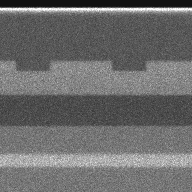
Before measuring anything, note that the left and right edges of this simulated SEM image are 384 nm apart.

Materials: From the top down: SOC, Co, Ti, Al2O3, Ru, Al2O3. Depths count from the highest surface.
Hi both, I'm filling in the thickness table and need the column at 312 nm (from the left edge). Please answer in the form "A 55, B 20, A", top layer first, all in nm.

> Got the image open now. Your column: SOC 106, Co 68, Ti 62, Al2O3 56, Ru 26, Al2O3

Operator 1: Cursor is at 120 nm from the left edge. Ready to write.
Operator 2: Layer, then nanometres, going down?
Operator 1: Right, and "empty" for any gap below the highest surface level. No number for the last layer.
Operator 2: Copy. SOC 106, Co 68, Ti 62, Al2O3 56, Ru 26, Al2O3